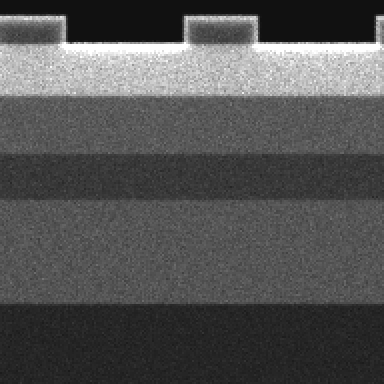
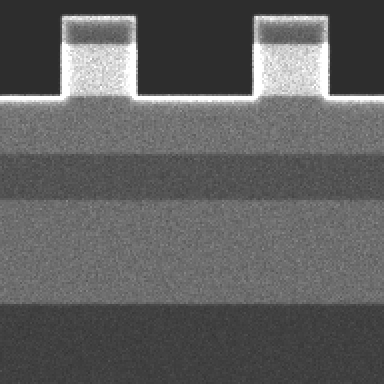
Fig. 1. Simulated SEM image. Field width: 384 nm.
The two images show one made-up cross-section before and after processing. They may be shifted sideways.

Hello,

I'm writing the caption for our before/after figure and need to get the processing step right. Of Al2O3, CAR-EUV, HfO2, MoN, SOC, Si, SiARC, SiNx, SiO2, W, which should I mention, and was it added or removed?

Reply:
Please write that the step removed HfO2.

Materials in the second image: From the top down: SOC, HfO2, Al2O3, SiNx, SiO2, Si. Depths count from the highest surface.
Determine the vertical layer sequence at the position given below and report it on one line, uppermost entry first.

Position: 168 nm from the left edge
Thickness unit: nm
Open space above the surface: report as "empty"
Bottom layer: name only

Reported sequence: empty 80, Al2O3 58, SiNx 46, SiO2 104, Si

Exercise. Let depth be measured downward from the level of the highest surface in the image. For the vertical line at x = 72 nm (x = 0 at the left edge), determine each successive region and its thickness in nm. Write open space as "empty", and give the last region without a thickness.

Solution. SOC 28, HfO2 52, Al2O3 58, SiNx 46, SiO2 104, Si